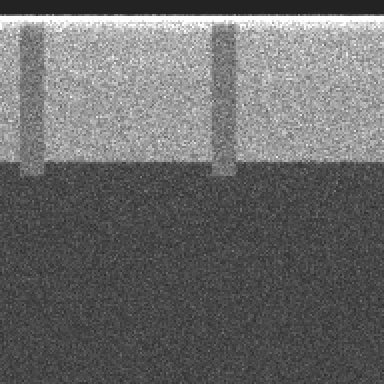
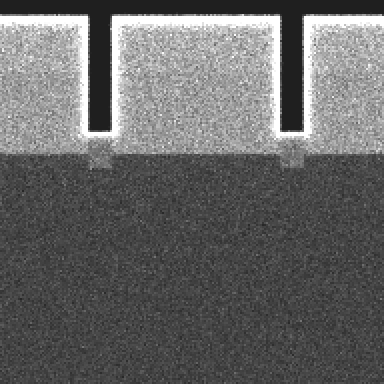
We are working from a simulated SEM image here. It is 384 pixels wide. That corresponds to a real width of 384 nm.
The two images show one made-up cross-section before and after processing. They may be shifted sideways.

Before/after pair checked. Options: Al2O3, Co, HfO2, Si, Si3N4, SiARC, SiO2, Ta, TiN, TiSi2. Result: removed SiARC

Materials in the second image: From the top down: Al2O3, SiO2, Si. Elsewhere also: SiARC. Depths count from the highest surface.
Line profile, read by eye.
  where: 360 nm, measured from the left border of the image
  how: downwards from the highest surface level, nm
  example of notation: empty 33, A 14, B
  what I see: Al2O3 56, SiO2 82, Si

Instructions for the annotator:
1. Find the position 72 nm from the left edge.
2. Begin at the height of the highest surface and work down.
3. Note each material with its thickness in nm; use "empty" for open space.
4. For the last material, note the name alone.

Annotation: Al2O3 56, SiO2 82, Si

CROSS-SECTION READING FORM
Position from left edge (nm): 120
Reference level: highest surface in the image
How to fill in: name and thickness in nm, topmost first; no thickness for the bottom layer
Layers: Al2O3 56, SiO2 82, Si